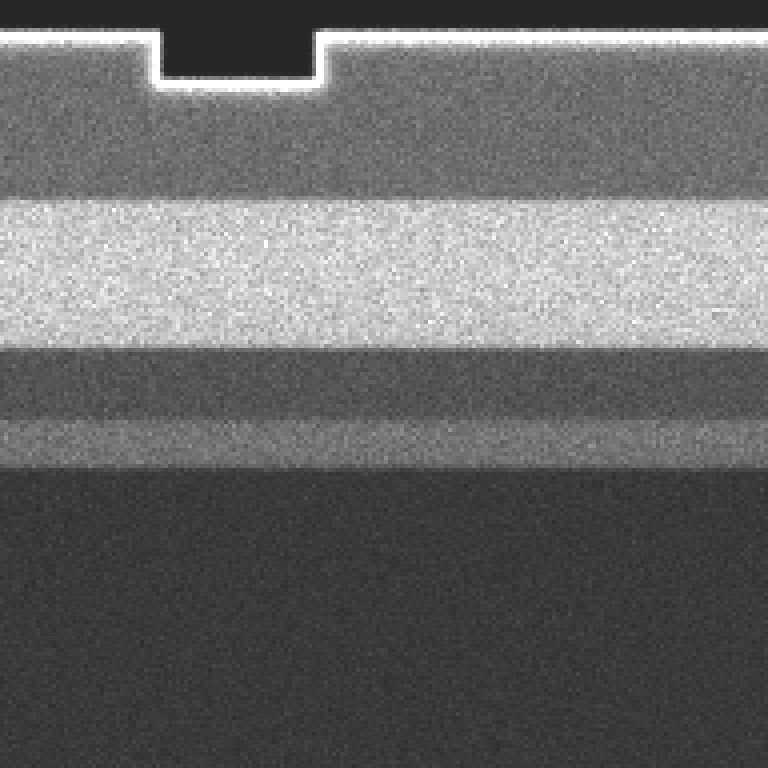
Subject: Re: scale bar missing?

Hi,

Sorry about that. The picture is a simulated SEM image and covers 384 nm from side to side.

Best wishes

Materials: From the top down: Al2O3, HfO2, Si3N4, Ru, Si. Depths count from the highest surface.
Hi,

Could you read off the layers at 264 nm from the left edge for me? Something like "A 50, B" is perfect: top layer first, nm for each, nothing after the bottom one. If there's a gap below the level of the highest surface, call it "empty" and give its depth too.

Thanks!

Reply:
Al2O3 84, HfO2 74, Si3N4 36, Ru 24, Si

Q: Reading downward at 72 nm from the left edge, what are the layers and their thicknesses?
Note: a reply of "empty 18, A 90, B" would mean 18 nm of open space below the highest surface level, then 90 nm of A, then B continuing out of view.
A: Al2O3 84, HfO2 74, Si3N4 36, Ru 24, Si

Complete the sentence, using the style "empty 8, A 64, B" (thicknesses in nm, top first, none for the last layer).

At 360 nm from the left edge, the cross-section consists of Al2O3 84, HfO2 74, Si3N4 36, Ru 24, Si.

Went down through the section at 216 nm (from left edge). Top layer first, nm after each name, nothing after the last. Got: Al2O3 84, HfO2 74, Si3N4 36, Ru 24, Si